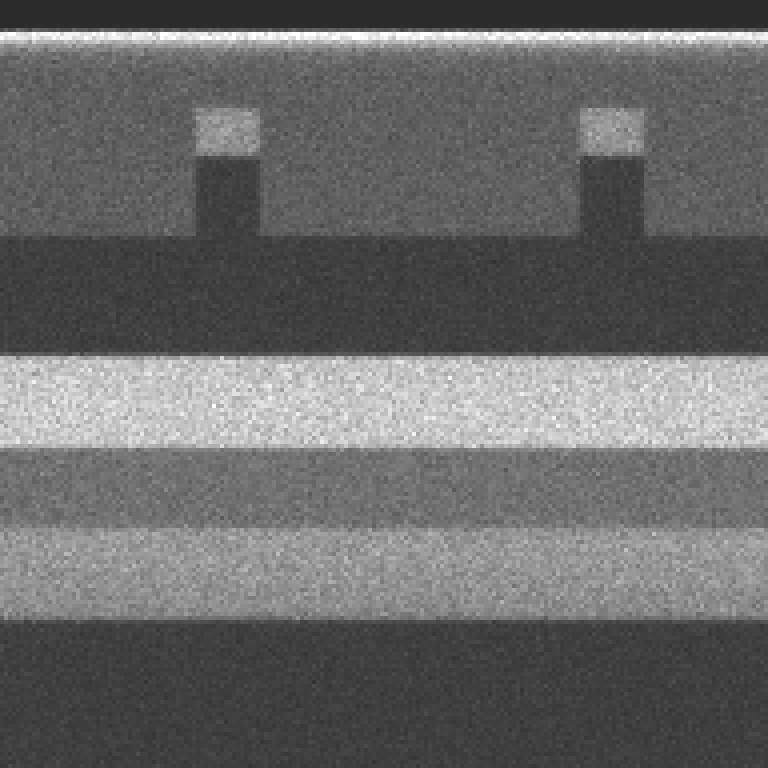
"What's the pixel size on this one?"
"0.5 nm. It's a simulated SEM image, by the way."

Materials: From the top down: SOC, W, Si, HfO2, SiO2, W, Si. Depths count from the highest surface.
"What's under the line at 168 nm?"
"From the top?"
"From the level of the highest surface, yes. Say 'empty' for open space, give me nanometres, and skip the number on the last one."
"SOC 102, Si 60, HfO2 46, SiO2 40, W 46, Si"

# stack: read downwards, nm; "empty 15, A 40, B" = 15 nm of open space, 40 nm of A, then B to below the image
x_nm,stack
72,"SOC 102, Si 60, HfO2 46, SiO2 40, W 46, Si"